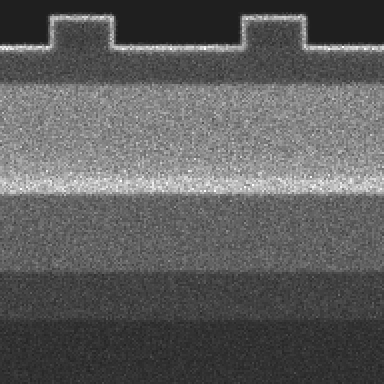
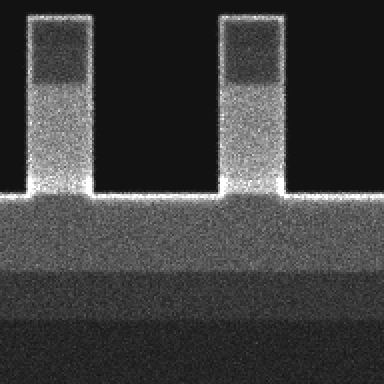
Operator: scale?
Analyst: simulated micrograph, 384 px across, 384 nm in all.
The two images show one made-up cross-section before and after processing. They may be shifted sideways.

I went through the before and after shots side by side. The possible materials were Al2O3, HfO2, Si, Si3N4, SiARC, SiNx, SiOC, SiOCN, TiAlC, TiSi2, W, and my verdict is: removed, HfO2 and Si3N4 and W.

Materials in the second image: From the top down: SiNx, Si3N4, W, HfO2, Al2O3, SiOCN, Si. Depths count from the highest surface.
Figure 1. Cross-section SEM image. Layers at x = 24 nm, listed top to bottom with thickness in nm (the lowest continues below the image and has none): empty 178, Al2O3 78, SiOCN 48, Si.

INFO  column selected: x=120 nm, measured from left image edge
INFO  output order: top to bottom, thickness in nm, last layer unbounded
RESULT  empty 178, Al2O3 78, SiOCN 48, Si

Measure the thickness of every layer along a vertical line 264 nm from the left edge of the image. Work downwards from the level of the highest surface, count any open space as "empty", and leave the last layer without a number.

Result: SiNx 30, Si3N4 38, W 94, HfO2 16, Al2O3 78, SiOCN 48, Si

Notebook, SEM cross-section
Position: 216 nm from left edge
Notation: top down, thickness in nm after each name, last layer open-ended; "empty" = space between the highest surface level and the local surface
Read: empty 178, Al2O3 78, SiOCN 48, Si